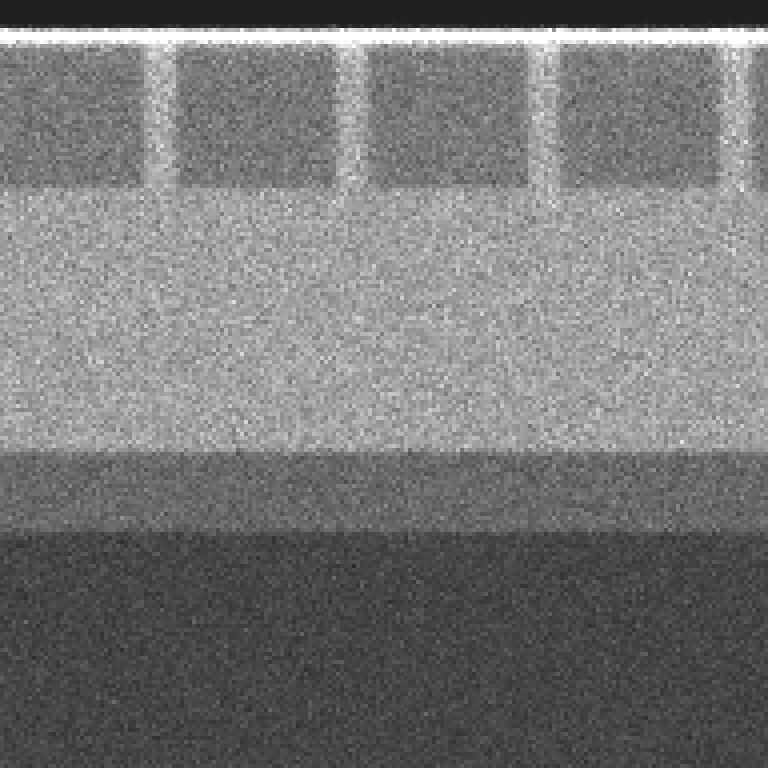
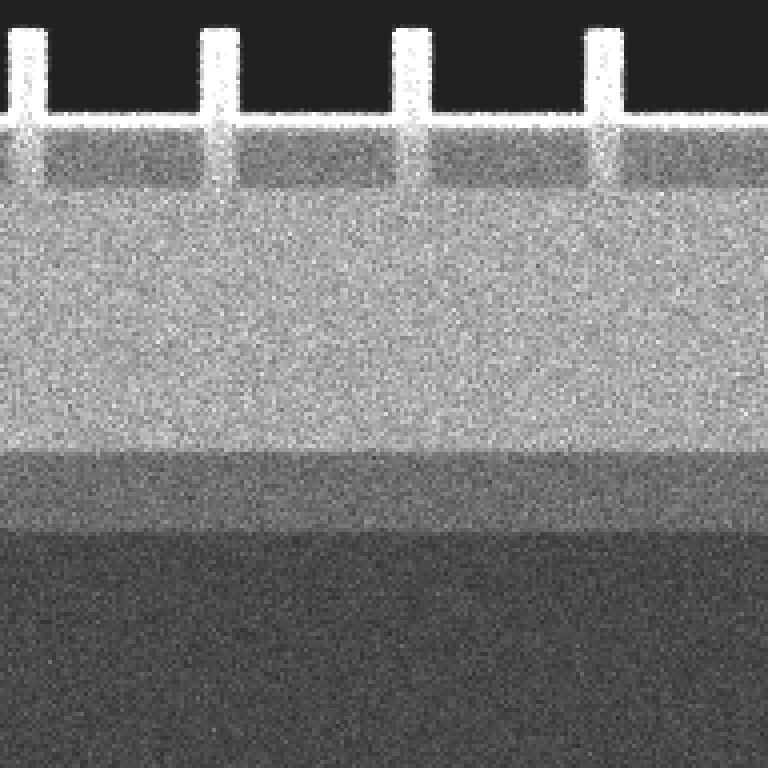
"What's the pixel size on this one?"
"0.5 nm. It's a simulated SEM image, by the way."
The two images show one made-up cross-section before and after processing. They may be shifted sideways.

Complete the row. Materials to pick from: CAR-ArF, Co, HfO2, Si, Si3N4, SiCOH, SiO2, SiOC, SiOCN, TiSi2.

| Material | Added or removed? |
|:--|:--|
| Si3N4 | removed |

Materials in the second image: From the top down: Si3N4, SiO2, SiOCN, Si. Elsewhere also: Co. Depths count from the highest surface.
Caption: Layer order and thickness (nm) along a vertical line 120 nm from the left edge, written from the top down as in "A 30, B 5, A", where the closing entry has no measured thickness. empty 42, Si3N4 36, SiO2 132, SiOCN 40, Si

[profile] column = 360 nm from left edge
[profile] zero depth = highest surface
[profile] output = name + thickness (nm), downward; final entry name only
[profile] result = empty 42, Si3N4 36, SiO2 132, SiOCN 40, Si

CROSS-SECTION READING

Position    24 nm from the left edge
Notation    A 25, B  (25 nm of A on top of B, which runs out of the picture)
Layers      empty 42, Si3N4 36, SiO2 132, SiOCN 40, Si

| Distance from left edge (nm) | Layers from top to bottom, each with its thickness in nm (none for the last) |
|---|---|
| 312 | empty 42, Si3N4 36, SiO2 132, SiOCN 40, Si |